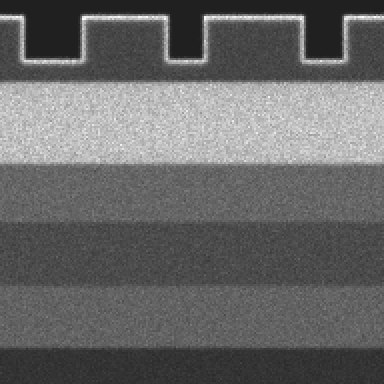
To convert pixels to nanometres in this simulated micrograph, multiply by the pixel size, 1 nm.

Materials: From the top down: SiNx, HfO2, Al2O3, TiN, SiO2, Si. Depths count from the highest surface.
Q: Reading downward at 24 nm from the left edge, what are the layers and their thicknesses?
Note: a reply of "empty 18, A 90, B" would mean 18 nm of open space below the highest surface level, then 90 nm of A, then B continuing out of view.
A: empty 44, SiNx 22, HfO2 82, Al2O3 58, TiN 64, SiO2 62, Si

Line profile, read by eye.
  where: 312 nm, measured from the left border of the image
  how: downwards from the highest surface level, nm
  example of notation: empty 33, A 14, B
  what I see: empty 44, SiNx 22, HfO2 82, Al2O3 58, TiN 64, SiO2 62, Si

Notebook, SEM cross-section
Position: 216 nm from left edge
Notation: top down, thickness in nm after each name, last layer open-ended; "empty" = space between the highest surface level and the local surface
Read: SiNx 66, HfO2 82, Al2O3 58, TiN 64, SiO2 62, Si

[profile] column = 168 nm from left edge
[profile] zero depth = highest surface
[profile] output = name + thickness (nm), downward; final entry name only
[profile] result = empty 44, SiNx 22, HfO2 82, Al2O3 58, TiN 64, SiO2 62, Si